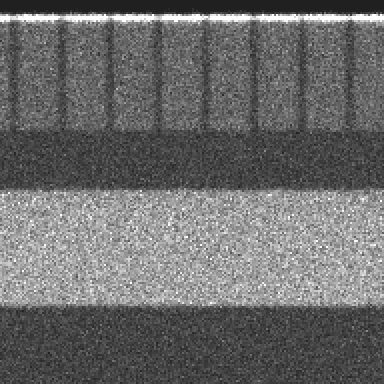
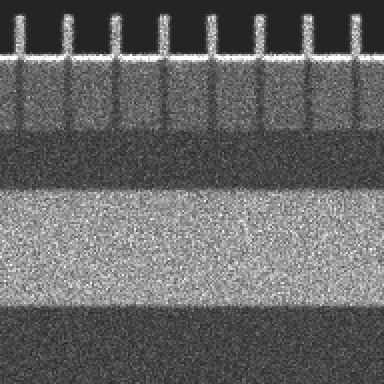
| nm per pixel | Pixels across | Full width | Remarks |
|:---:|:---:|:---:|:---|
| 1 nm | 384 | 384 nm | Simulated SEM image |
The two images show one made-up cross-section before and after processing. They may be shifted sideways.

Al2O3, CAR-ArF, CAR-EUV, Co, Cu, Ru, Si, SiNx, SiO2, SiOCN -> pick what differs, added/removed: SiNx removed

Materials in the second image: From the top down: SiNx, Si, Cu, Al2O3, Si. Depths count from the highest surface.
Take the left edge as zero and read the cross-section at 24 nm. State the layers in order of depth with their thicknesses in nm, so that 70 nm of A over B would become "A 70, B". empty 40, SiNx 74, Si 60, Cu 66, Al2O3 50, Si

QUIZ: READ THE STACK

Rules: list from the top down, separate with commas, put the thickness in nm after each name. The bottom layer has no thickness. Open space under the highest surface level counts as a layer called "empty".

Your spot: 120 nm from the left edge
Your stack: empty 40, SiNx 74, Si 60, Cu 66, Al2O3 50, Si